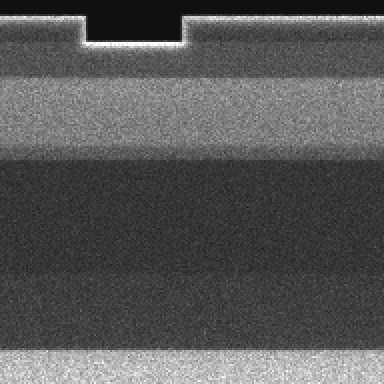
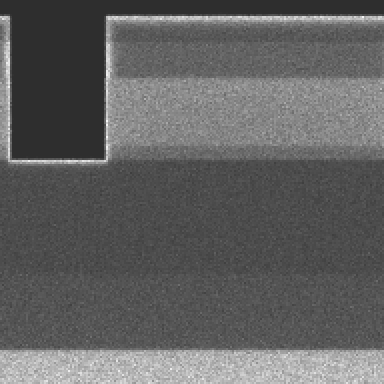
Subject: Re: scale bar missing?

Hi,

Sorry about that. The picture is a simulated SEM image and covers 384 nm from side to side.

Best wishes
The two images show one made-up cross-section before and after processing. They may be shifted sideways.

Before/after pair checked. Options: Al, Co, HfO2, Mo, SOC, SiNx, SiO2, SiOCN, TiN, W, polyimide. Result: removed Co and SiO2 and W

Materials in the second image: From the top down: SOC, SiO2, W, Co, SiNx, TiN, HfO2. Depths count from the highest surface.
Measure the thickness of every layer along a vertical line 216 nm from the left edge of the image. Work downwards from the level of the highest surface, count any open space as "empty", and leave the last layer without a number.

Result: SOC 26, SiO2 36, W 68, Co 14, SiNx 114, TiN 76, HfO2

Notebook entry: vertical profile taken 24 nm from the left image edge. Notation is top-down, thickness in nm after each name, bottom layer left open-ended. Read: empty 144, SiNx 114, TiN 76, HfO2